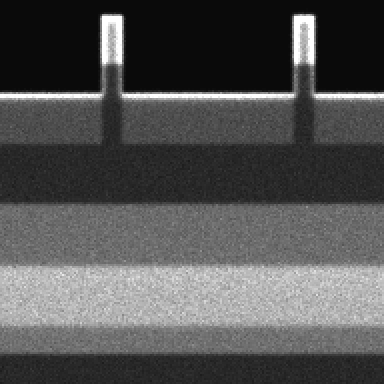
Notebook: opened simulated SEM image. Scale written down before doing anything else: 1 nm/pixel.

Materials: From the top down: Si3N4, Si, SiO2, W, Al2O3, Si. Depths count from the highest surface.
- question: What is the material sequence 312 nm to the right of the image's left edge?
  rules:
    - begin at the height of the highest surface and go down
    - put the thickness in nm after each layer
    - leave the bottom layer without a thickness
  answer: Al2O3 48, Si 140, SiO2 62, W 60, Al2O3 28, Si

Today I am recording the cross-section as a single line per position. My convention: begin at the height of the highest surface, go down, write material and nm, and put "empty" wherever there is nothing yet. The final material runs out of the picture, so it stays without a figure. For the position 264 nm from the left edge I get empty 78, Si3N4 50, Si 60, SiO2 62, W 60, Al2O3 28, Si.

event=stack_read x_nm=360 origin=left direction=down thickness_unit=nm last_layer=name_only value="empty 78, Si3N4 50, Si 60, SiO2 62, W 60, Al2O3 28, Si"